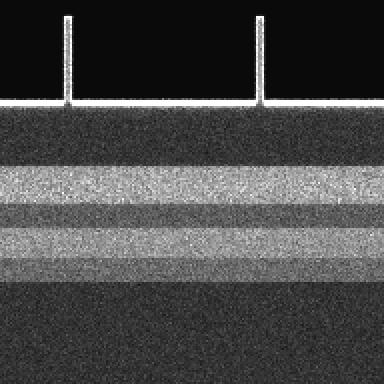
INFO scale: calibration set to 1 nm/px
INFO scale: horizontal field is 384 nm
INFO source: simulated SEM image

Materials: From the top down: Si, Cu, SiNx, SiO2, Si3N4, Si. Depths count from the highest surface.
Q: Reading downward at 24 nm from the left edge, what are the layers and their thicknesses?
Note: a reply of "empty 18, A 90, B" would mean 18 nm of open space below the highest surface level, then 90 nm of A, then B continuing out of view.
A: empty 84, Si 66, Cu 38, SiNx 24, SiO2 30, Si3N4 24, Si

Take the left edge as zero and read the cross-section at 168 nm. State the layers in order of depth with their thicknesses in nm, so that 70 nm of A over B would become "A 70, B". empty 84, Si 66, Cu 38, SiNx 24, SiO2 30, Si3N4 24, Si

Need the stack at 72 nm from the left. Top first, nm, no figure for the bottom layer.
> empty 84, Si 66, Cu 38, SiNx 24, SiO2 30, Si3N4 24, Si